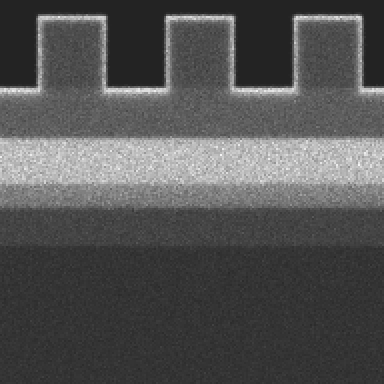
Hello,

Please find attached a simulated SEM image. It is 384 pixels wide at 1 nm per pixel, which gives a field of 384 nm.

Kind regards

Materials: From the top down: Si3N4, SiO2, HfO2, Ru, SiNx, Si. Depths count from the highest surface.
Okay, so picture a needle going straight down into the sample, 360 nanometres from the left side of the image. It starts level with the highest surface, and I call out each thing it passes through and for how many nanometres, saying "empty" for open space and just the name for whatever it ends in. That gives Si3N4 72, SiO2 50, HfO2 46, Ru 24, SiNx 38, Si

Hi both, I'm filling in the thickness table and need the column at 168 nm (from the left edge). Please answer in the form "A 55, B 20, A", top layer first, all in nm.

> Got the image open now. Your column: Si3N4 72, SiO2 50, HfO2 46, Ru 24, SiNx 38, Si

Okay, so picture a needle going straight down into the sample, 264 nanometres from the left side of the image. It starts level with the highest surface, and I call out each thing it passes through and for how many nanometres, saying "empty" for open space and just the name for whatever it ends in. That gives empty 72, SiO2 50, HfO2 46, Ru 24, SiNx 38, Si